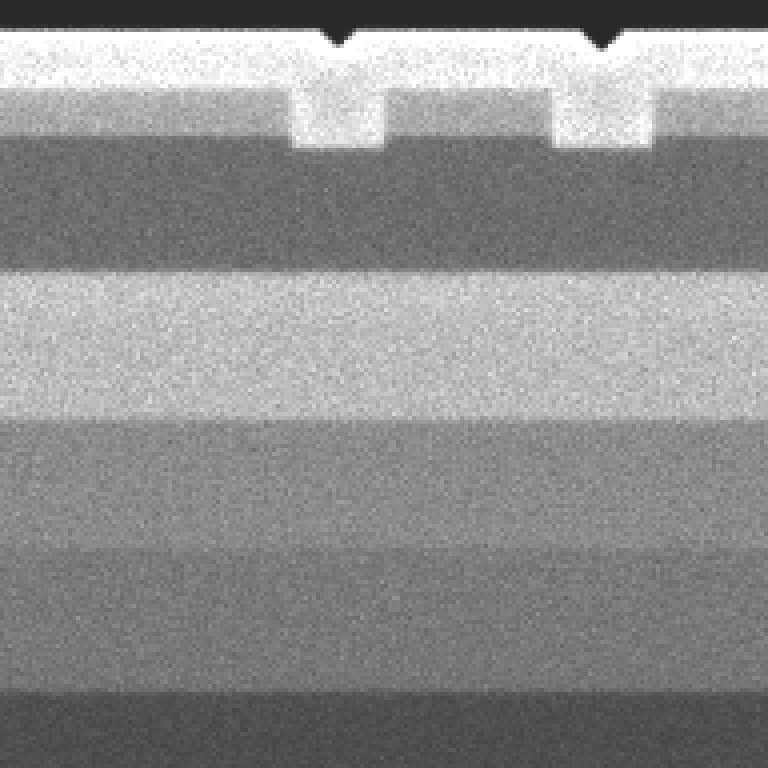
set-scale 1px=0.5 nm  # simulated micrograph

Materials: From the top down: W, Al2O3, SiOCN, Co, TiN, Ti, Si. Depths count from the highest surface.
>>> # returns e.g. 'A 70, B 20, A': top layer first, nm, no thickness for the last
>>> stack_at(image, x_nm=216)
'W 28, Al2O3 24, SiOCN 68, Co 74, TiN 64, Ti 72, Si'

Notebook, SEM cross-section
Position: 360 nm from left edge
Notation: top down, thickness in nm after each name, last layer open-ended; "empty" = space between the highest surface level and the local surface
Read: W 28, Al2O3 24, SiOCN 68, Co 74, TiN 64, Ti 72, Si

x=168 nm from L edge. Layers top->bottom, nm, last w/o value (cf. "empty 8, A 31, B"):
empty 8, W 50, SiOCN 62, Co 74, TiN 64, Ti 72, Si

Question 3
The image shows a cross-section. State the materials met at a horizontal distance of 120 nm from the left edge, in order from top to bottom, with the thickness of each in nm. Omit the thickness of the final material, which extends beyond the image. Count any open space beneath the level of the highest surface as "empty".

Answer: W 28, Al2O3 24, SiOCN 68, Co 74, TiN 64, Ti 72, Si